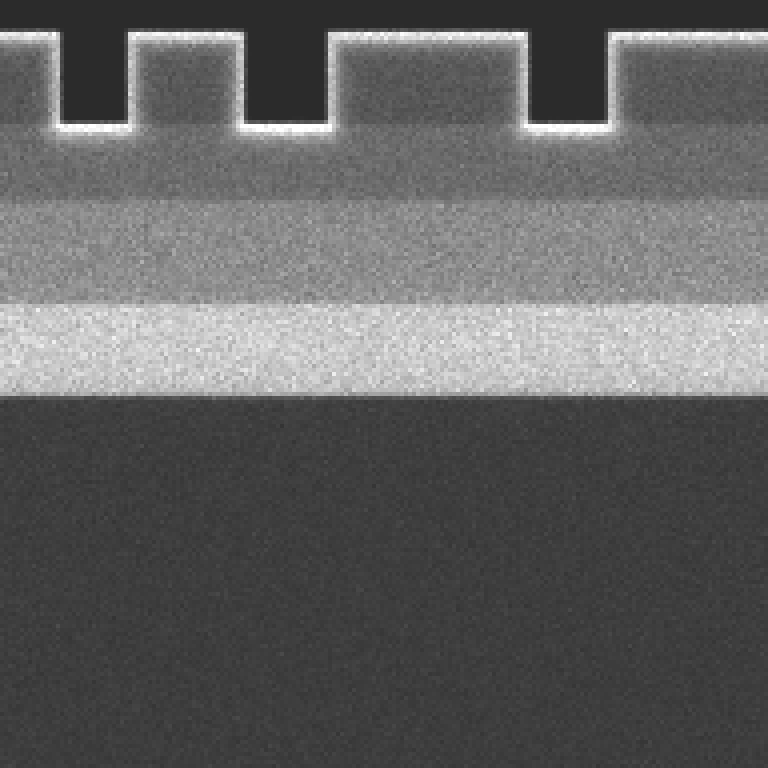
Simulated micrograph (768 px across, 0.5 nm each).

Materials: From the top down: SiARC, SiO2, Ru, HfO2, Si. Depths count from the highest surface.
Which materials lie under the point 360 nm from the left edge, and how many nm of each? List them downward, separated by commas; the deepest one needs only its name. SiARC 46, SiO2 38, Ru 52, HfO2 46, Si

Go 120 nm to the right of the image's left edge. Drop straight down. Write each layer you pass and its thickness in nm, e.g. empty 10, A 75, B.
SiARC 46, SiO2 38, Ru 52, HfO2 46, Si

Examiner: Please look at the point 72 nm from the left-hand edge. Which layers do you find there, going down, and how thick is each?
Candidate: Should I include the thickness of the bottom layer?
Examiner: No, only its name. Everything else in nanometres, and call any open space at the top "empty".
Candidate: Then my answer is SiARC 46, SiO2 38, Ru 52, HfO2 46, Si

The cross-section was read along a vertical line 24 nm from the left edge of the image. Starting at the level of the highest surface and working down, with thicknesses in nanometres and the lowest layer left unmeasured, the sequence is SiARC 46, SiO2 38, Ru 52, HfO2 46, Si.